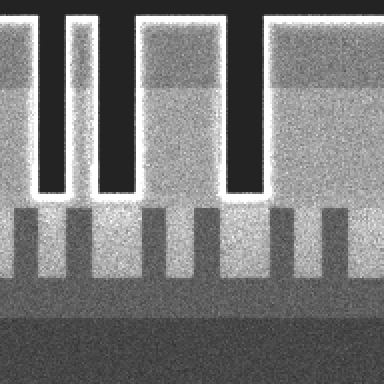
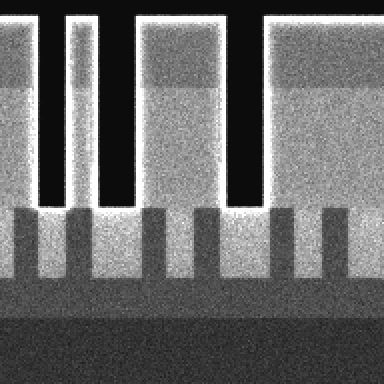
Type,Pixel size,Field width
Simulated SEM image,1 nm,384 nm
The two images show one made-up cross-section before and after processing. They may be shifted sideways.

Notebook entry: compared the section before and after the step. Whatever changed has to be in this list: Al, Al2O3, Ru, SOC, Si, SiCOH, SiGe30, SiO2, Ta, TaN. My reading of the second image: Al2O3 removed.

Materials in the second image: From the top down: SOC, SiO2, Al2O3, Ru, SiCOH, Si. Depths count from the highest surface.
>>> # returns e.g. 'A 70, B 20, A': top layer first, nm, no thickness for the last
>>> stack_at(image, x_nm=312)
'SOC 72, SiO2 106, Al2O3 14, Ru 70, SiCOH 40, Si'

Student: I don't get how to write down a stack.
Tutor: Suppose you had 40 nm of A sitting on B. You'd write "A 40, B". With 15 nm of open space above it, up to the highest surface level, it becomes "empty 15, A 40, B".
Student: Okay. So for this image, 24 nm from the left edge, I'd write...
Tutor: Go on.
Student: SOC 72, SiO2 106, Al2O3 14, SiCOH 110, Si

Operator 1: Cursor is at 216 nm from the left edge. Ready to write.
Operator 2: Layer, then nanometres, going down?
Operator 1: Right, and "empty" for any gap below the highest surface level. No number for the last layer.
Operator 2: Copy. SOC 72, SiO2 106, Al2O3 14, SiCOH 110, Si